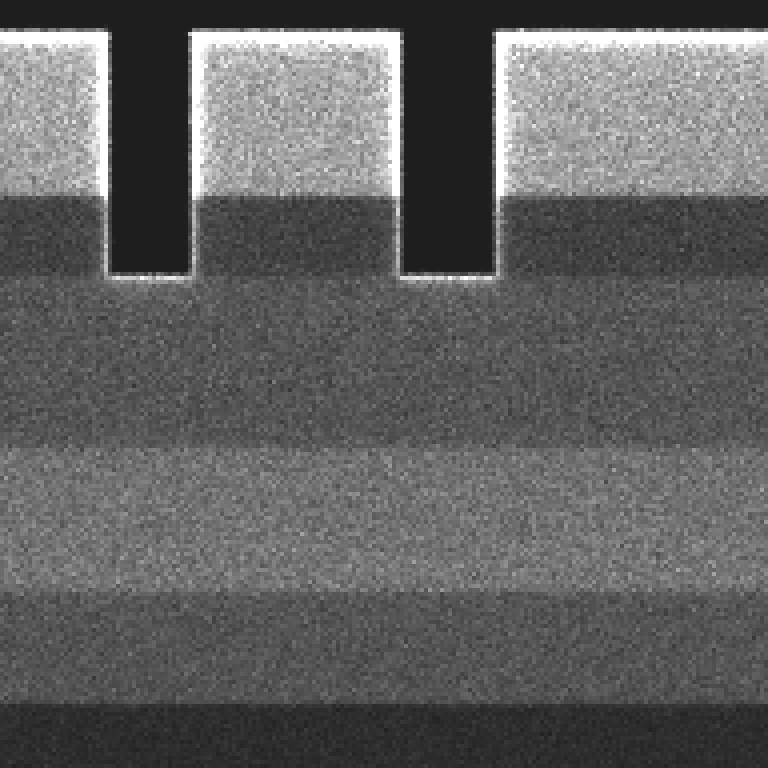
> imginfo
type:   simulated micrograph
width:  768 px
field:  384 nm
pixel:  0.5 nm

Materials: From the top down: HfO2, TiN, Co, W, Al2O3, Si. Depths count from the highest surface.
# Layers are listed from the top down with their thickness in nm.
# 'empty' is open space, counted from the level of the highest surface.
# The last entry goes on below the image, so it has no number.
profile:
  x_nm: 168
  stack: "HfO2 82, TiN 40, Co 86, W 72, Al2O3 56, Si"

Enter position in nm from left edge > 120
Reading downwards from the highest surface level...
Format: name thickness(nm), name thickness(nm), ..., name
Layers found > HfO2 82, TiN 40, Co 86, W 72, Al2O3 56, Si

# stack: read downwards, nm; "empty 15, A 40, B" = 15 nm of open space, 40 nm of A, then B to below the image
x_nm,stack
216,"empty 122, Co 86, W 72, Al2O3 56, Si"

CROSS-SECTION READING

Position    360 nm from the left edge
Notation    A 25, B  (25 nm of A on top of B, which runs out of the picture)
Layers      HfO2 82, TiN 40, Co 86, W 72, Al2O3 56, Si